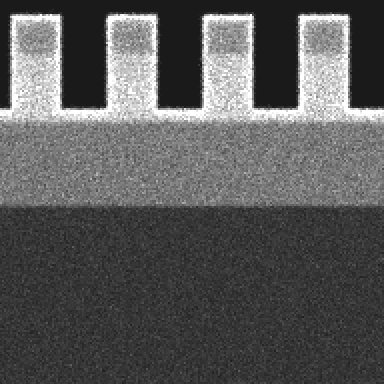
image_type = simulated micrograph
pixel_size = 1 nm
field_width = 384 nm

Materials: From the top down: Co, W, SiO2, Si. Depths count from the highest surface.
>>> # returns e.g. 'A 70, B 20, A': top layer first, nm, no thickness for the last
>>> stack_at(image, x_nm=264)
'empty 94, W 12, SiO2 84, Si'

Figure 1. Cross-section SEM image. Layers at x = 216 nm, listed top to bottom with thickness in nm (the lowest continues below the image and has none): Co 38, W 68, SiO2 84, Si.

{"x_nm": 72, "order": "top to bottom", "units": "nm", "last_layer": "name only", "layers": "empty 94, W 12, SiO2 84, Si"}